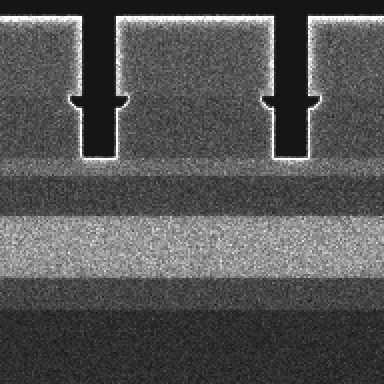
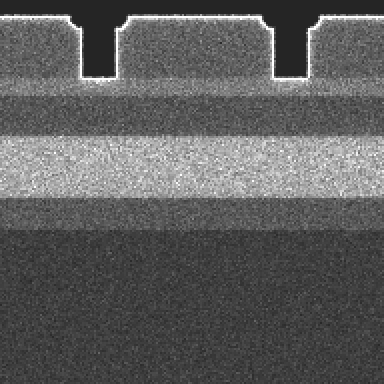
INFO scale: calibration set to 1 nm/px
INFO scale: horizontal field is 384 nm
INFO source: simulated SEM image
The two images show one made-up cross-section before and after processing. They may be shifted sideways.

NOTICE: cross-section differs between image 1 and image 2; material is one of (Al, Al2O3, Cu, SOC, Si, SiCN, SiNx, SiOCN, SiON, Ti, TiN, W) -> removed: SOC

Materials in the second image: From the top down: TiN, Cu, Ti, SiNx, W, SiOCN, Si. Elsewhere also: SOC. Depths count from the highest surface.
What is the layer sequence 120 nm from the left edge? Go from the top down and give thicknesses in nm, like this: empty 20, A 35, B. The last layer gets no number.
empty 12, TiN 50, Cu 18, Ti 30, SiNx 10, W 62, SiOCN 32, Si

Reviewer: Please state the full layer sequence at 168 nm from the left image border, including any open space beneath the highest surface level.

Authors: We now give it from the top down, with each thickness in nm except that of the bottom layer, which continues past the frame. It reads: TiN 62, Cu 18, Ti 30, SiNx 10, W 62, SiOCN 32, Si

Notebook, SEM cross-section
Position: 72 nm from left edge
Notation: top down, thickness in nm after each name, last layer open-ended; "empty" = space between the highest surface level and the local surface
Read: empty 8, TiN 54, Cu 18, Ti 30, SiNx 10, W 62, SiOCN 32, Si